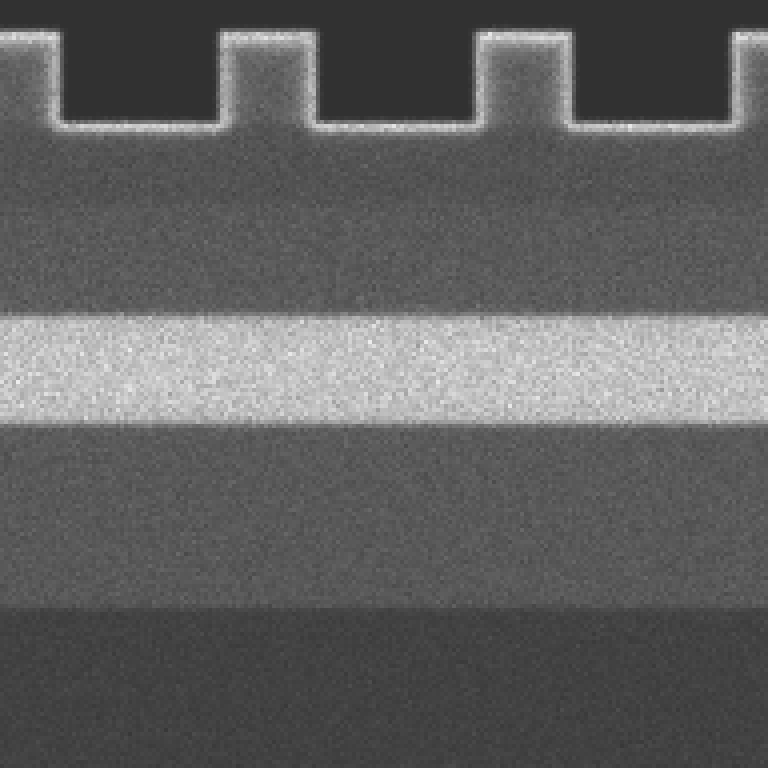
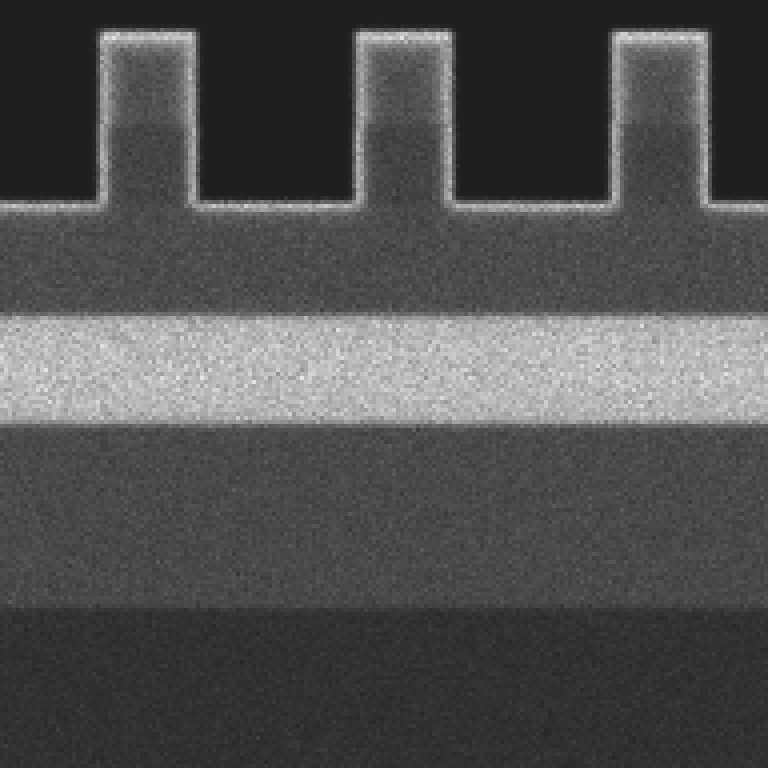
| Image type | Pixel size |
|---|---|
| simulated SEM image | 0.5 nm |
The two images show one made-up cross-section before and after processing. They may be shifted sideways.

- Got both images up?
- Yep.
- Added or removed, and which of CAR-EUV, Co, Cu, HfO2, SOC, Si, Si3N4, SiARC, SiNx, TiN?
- removed, SiNx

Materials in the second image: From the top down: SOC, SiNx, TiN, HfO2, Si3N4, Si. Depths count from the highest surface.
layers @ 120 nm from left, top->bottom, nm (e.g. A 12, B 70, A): empty 86, TiN 56, HfO2 54, Si3N4 92, Si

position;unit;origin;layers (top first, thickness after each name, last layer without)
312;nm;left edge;SOC 46, SiNx 40, TiN 56, HfO2 54, Si3N4 92, Si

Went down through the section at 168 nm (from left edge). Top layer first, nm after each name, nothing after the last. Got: empty 86, TiN 56, HfO2 54, Si3N4 92, Si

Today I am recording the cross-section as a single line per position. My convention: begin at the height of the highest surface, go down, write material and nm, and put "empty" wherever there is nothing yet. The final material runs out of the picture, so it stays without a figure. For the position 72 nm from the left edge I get SOC 46, SiNx 40, TiN 56, HfO2 54, Si3N4 92, Si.